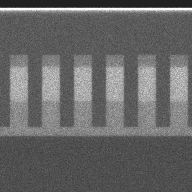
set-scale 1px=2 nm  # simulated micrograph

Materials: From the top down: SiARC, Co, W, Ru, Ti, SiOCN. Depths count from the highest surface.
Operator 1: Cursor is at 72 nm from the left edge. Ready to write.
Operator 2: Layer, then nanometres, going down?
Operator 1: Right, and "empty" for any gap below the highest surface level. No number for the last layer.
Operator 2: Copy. SiARC 238, Ru 18, Ti 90, SiOCN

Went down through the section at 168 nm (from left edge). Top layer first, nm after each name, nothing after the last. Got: SiARC 94, Co 24, W 68, Ru 70, Ti 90, SiOCN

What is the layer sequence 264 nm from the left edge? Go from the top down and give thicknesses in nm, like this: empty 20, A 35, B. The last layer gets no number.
SiARC 238, Ru 18, Ti 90, SiOCN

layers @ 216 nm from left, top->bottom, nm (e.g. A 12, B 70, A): SiARC 94, Co 24, W 68, Ru 70, Ti 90, SiOCN